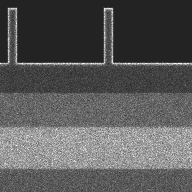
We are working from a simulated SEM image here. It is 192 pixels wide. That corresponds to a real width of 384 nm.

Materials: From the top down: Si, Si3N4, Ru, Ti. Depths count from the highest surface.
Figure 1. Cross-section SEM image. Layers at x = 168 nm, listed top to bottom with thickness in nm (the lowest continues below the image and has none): empty 110, Si 60, Si3N4 68, Ru 84, Ti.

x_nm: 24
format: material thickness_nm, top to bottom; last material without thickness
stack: Si 170, Si3N4 68, Ru 84, Ti